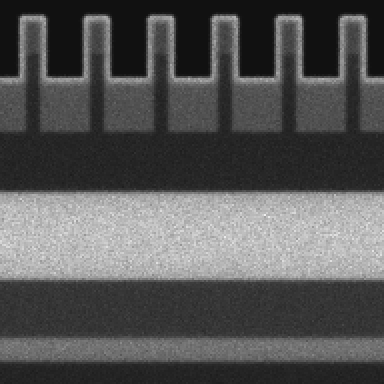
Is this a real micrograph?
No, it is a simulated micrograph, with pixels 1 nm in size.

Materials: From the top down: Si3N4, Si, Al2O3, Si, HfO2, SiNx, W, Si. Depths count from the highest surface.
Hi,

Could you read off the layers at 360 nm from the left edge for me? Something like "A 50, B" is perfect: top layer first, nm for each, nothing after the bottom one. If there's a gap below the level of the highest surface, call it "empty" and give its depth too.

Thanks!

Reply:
Si3N4 38, Si 30, Al2O3 48, Si 60, HfO2 88, SiNx 58, W 24, Si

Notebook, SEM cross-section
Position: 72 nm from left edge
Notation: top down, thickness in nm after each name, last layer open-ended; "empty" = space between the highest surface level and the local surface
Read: empty 62, Al2O3 54, Si 60, HfO2 88, SiNx 58, W 24, Si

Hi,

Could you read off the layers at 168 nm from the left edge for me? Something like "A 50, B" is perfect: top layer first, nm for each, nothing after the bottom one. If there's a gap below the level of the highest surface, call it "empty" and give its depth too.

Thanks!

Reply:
Si3N4 38, Si 30, Al2O3 48, Si 60, HfO2 88, SiNx 58, W 24, Si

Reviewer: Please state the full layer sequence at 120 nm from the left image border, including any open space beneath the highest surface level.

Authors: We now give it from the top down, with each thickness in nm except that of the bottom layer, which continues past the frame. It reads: empty 62, Al2O3 54, Si 60, HfO2 88, SiNx 58, W 24, Si